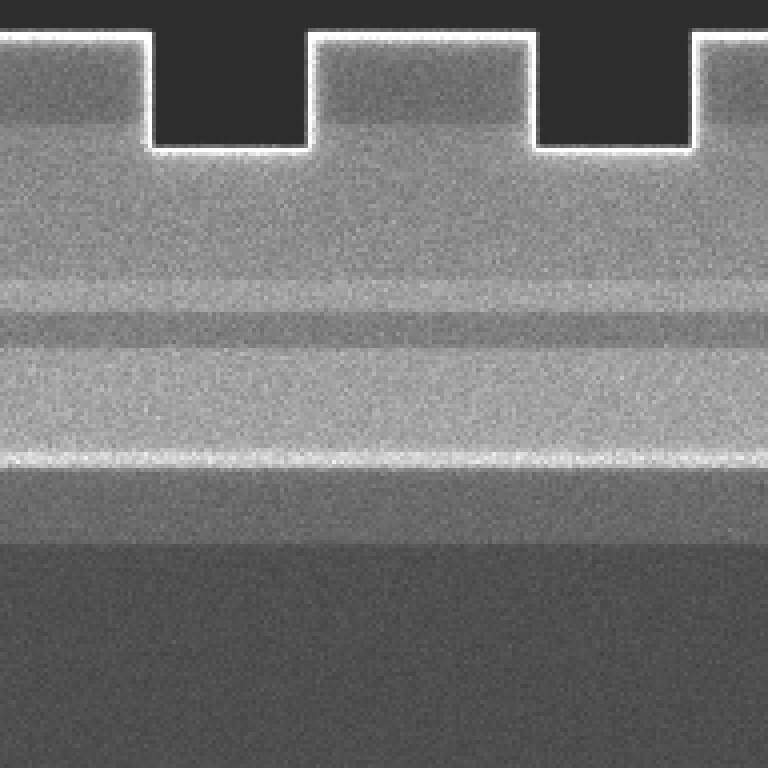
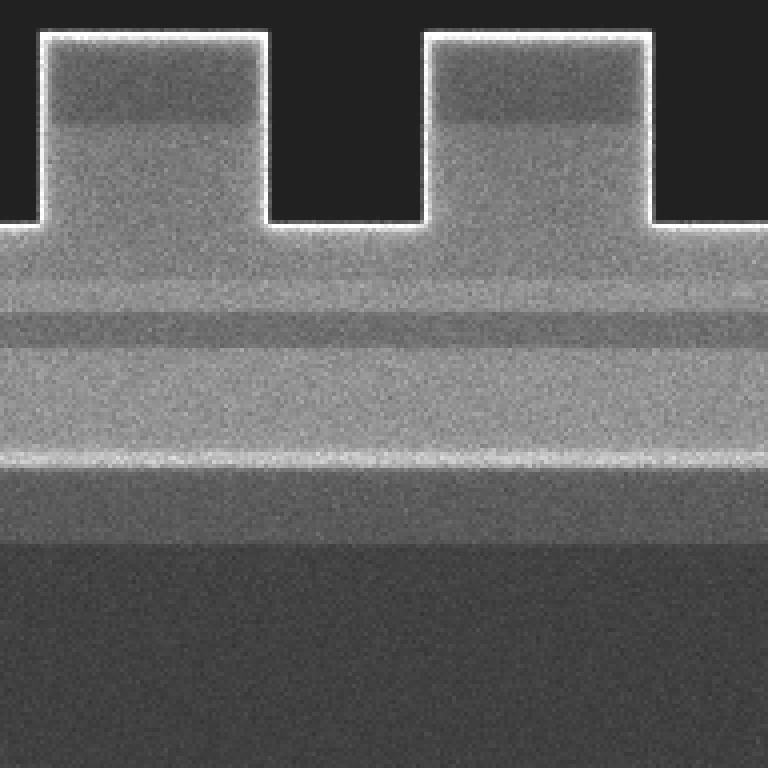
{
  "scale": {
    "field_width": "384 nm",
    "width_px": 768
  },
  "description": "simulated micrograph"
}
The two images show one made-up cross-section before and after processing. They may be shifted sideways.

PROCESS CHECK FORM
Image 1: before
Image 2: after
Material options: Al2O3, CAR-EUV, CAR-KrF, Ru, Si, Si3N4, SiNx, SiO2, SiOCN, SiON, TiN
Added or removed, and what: removed, TiN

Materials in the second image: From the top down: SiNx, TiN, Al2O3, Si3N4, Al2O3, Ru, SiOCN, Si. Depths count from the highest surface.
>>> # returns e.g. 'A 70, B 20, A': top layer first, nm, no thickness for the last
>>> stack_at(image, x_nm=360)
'empty 96, TiN 28, Al2O3 16, Si3N4 18, Al2O3 52, Ru 8, SiOCN 38, Si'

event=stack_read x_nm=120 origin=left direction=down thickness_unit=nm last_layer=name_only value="SiNx 46, TiN 78, Al2O3 16, Si3N4 18, Al2O3 52, Ru 8, SiOCN 38, Si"